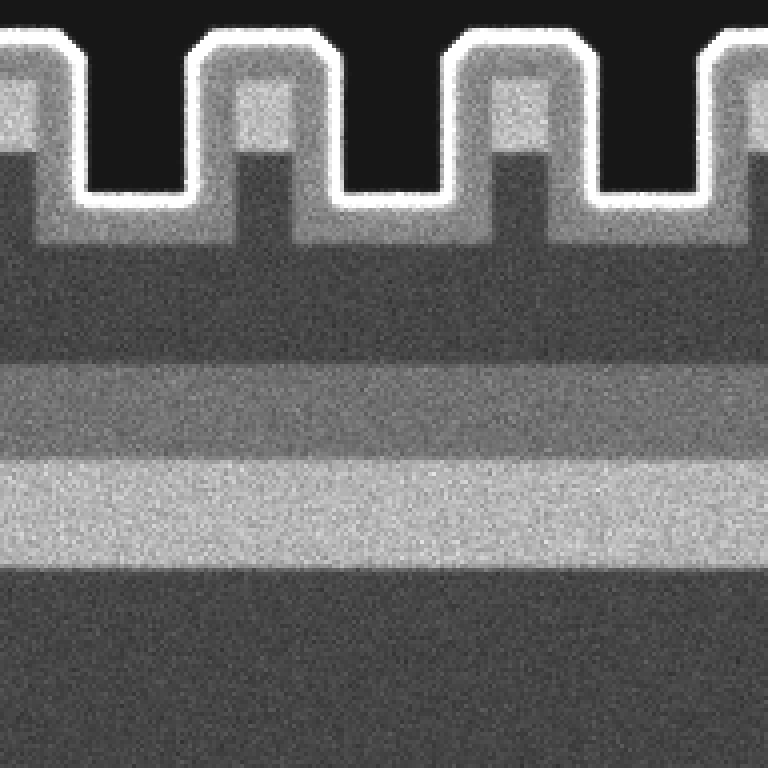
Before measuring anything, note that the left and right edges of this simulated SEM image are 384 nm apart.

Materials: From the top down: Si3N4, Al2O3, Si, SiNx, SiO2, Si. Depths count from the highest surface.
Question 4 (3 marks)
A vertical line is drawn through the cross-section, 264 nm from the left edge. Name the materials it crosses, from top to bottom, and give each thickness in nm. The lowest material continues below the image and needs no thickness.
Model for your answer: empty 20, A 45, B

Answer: Si3N4 24, Al2O3 36, Si 106, SiNx 48, SiO2 54, Si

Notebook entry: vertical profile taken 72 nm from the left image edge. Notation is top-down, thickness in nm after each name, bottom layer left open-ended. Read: empty 82, Si3N4 24, Si 60, SiNx 48, SiO2 54, Si